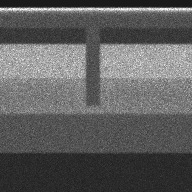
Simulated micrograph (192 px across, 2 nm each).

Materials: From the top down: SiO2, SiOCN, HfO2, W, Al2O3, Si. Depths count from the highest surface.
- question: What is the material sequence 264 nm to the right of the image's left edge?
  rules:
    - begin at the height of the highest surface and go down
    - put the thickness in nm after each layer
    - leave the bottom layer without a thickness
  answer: SiO2 40, SiOCN 32, HfO2 68, W 72, Al2O3 78, Si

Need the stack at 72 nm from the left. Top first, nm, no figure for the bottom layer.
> SiO2 40, SiOCN 32, HfO2 68, W 72, Al2O3 78, Si